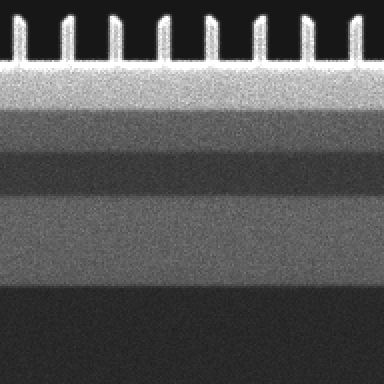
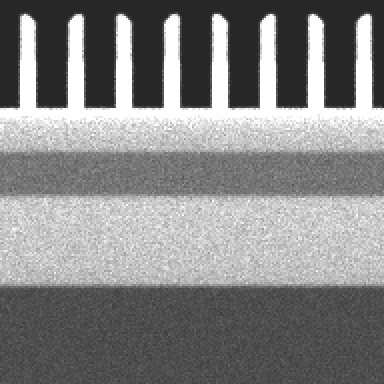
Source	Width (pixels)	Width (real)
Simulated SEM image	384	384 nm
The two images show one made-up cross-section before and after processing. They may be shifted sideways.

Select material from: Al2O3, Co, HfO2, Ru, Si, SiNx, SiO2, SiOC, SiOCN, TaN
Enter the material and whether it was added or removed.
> HfO2 / removed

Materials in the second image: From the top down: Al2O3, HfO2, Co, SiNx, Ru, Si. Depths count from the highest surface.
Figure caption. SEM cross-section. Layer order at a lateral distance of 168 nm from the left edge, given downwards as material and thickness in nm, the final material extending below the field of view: empty 4, Al2O3 42, HfO2 48, Co 42, SiNx 44, Ru 90, Si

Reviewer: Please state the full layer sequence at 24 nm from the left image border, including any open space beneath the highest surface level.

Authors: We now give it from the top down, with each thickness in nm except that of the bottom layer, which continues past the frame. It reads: Al2O3 46, HfO2 48, Co 42, SiNx 44, Ru 90, Si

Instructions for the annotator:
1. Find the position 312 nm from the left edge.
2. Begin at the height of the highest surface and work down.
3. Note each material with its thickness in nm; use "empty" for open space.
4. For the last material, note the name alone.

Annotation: Al2O3 46, HfO2 48, Co 42, SiNx 44, Ru 90, Si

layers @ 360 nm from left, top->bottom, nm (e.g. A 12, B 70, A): empty 4, Al2O3 42, HfO2 48, Co 42, SiNx 44, Ru 90, Si